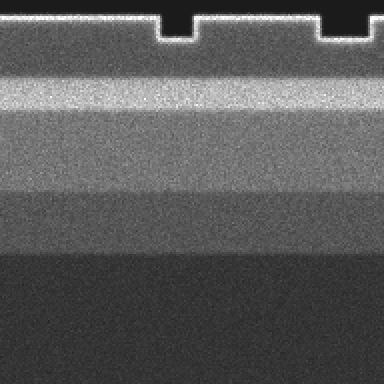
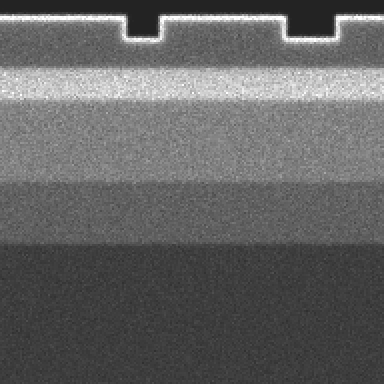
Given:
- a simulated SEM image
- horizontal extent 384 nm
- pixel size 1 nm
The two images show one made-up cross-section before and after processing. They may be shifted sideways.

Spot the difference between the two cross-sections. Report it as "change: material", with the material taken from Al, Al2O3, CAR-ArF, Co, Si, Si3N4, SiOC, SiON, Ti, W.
removed: Si3N4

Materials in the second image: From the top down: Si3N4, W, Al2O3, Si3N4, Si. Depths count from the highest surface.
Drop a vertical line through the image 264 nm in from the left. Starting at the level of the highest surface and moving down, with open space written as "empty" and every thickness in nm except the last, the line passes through Si3N4 52, W 32, Al2O3 82, Si3N4 62, Si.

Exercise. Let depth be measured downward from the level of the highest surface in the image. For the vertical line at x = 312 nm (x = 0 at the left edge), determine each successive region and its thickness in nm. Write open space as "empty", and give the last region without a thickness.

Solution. empty 22, Si3N4 30, W 32, Al2O3 82, Si3N4 62, Si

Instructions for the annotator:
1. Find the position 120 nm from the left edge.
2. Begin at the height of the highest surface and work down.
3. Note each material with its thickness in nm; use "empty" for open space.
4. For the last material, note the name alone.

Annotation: Si3N4 52, W 32, Al2O3 82, Si3N4 62, Si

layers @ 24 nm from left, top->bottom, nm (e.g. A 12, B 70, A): Si3N4 52, W 32, Al2O3 82, Si3N4 62, Si